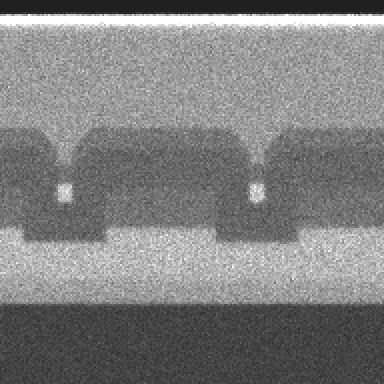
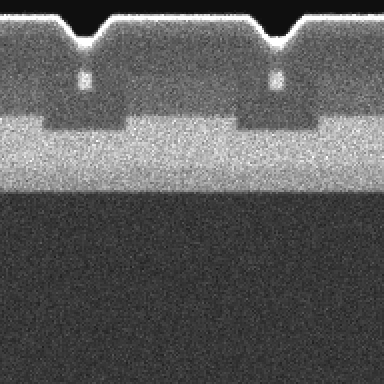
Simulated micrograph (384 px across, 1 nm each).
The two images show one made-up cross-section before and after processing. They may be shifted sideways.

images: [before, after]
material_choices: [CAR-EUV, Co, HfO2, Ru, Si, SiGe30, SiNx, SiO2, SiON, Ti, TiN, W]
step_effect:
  removed: SiO2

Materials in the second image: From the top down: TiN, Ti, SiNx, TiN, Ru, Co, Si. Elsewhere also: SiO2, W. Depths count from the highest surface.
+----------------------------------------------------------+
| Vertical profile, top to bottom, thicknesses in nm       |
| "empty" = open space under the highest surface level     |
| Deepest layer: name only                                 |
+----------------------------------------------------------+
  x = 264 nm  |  empty 18, TiN 20, Ti 50, SiNx 26, Ru 38, Co 24, Si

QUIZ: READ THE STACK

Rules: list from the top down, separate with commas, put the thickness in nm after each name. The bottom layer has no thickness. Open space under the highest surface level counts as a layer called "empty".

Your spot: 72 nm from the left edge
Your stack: empty 18, TiN 20, Ti 50, SiNx 26, Ru 38, Co 24, Si